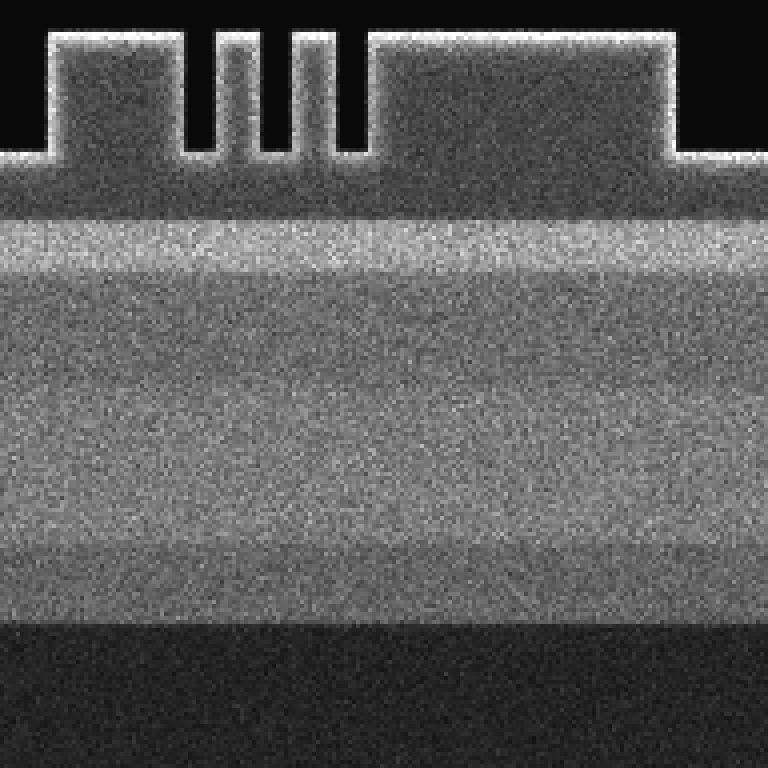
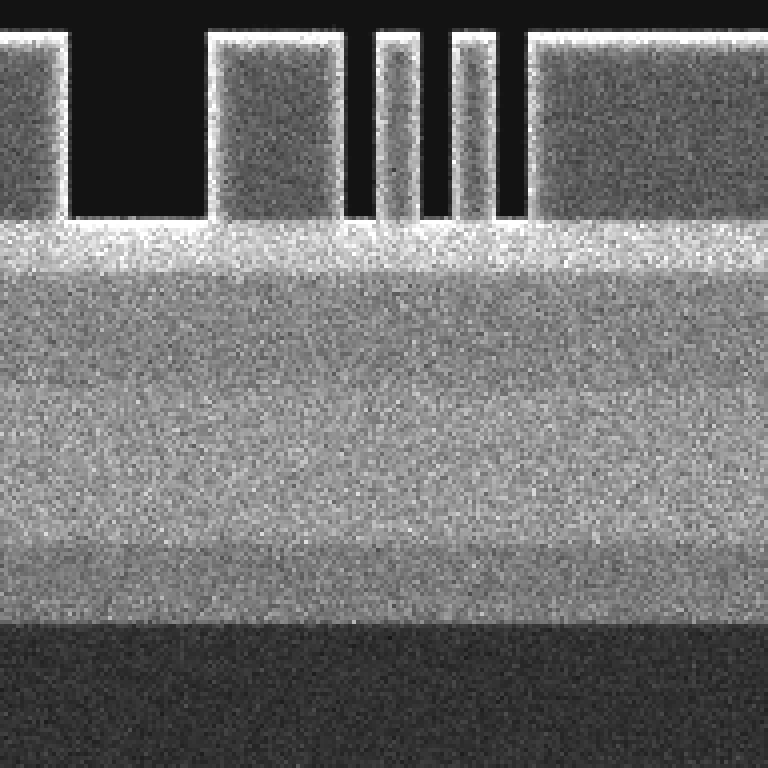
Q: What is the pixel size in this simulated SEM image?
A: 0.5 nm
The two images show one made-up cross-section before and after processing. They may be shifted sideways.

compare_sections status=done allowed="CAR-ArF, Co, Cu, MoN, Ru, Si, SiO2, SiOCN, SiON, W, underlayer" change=removed material="underlayer"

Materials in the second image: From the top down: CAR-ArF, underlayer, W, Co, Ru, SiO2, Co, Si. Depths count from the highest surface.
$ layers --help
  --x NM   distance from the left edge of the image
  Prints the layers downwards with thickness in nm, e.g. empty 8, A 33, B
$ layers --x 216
empty 94, W 26, Co 58, Ru 78, SiO2 28, Co 12, Si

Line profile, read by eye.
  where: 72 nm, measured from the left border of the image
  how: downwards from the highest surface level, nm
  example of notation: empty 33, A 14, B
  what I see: empty 94, W 26, Co 58, Ru 78, SiO2 28, Co 12, Si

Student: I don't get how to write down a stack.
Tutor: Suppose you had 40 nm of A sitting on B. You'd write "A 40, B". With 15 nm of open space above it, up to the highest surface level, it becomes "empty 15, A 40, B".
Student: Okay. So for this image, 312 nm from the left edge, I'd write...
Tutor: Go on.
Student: CAR-ArF 60, underlayer 34, W 26, Co 58, Ru 78, SiO2 28, Co 12, Si